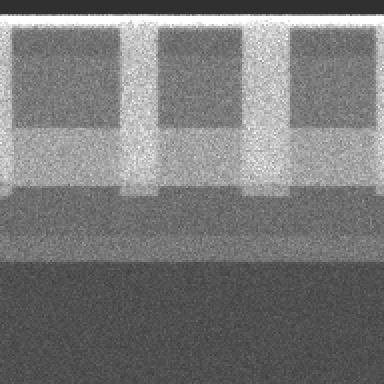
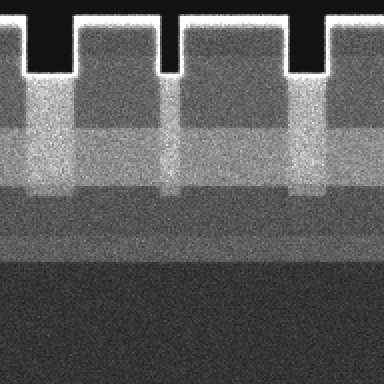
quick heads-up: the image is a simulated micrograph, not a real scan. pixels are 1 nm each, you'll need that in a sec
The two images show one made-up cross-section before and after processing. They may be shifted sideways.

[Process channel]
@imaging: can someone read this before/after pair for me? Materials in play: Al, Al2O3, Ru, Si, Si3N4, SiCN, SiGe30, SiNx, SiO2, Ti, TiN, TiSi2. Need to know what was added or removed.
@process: Ru removed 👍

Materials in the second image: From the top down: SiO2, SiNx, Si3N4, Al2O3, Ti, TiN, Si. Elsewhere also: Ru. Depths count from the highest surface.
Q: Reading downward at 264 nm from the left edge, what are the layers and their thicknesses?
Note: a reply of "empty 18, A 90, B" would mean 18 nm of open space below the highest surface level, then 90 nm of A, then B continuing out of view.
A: SiO2 12, SiNx 28, Si3N4 72, Al2O3 58, Ti 50, TiN 26, Si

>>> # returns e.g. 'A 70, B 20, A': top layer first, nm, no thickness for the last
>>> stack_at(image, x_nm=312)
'empty 58, Ru 110, SiO2 12, SiNx 28, Ti 12, TiN 26, Si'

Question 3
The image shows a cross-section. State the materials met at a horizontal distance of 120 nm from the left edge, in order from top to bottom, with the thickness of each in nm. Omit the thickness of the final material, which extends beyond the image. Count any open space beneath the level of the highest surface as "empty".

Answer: SiO2 12, SiNx 28, Si3N4 72, Al2O3 58, Ti 50, TiN 26, Si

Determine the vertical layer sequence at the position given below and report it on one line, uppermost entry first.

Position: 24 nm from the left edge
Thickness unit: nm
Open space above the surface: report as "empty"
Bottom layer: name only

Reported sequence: SiO2 12, SiNx 28, Si3N4 72, Al2O3 58, Ti 50, TiN 26, Si